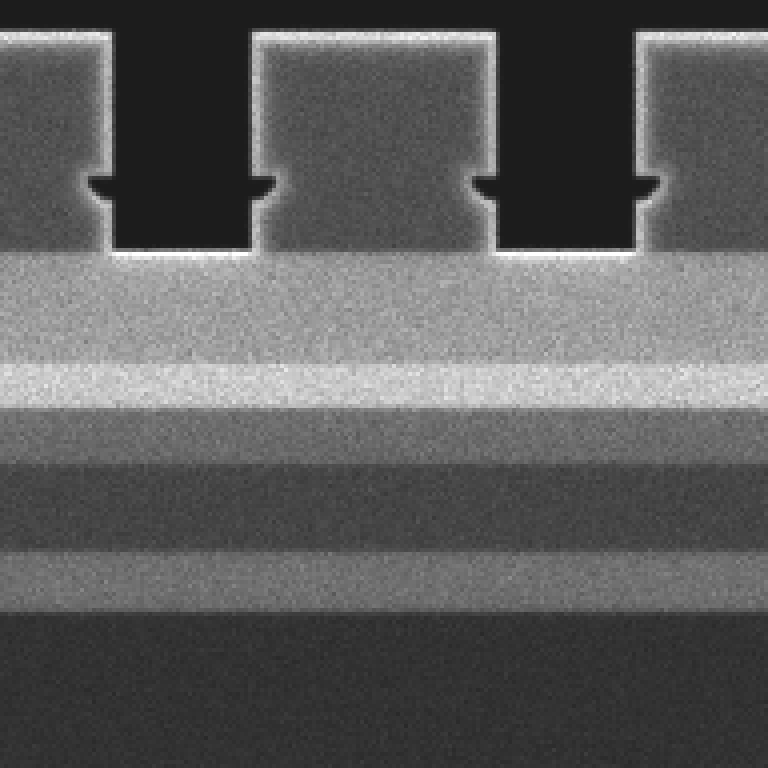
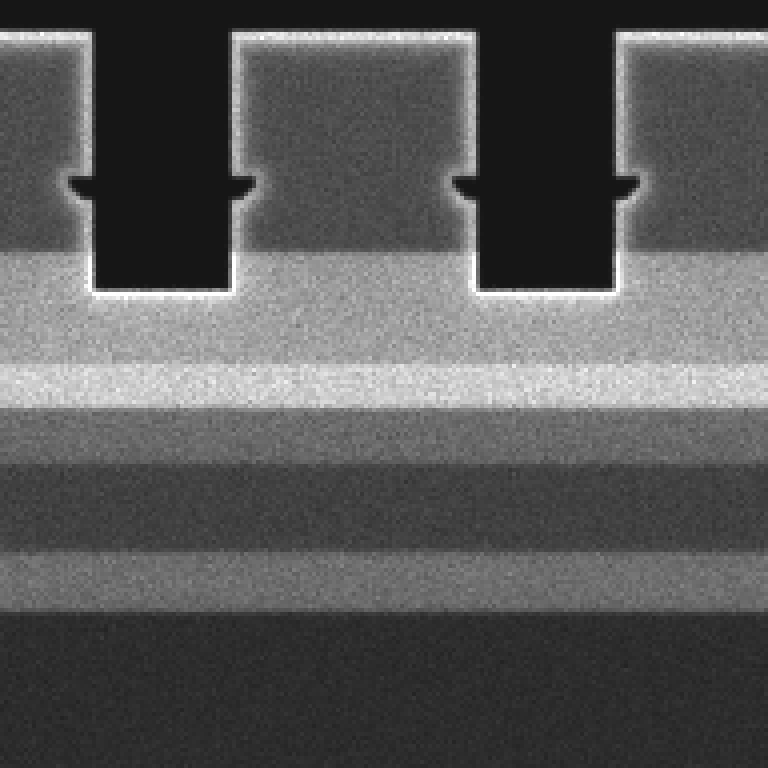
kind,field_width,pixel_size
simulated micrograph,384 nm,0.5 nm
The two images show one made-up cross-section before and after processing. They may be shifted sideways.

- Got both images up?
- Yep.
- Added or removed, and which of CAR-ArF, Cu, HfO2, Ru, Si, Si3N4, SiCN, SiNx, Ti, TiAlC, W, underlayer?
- removed, W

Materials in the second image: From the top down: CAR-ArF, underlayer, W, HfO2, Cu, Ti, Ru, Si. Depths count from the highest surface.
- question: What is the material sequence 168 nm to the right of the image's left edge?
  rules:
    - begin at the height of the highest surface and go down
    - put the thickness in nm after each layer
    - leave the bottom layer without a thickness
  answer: CAR-ArF 72, underlayer 38, W 56, HfO2 22, Cu 28, Ti 44, Ru 30, Si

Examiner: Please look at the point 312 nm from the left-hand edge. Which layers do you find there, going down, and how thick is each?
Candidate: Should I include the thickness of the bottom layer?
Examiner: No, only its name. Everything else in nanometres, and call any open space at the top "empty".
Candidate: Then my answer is CAR-ArF 72, empty 12, underlayer 26, W 56, HfO2 22, Cu 28, Ti 44, Ru 30, Si